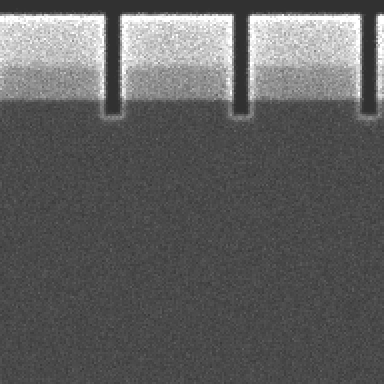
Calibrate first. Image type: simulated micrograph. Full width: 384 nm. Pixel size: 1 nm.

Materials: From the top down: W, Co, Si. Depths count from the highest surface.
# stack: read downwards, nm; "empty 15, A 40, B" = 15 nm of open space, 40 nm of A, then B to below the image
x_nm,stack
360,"empty 100, Si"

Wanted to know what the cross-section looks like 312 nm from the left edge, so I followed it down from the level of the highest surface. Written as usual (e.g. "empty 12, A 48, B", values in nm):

W 50, Co 34, Si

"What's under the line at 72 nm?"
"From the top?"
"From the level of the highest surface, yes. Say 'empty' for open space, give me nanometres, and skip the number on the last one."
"W 50, Co 34, Si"